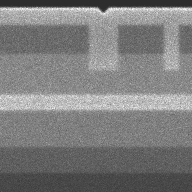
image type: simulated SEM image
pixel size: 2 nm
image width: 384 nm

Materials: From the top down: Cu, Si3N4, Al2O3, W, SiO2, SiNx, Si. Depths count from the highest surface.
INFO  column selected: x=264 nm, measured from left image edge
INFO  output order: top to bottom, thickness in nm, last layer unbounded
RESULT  Cu 34, Si3N4 58, Al2O3 82, W 30, SiO2 74, SiNx 52, Si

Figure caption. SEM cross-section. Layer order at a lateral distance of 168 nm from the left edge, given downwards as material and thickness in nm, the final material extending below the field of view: Cu 34, Si3N4 58, Al2O3 82, W 30, SiO2 74, SiNx 52, Si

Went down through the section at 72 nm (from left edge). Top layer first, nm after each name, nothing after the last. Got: Cu 34, Si3N4 58, Al2O3 82, W 30, SiO2 74, SiNx 52, Si